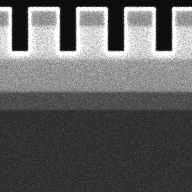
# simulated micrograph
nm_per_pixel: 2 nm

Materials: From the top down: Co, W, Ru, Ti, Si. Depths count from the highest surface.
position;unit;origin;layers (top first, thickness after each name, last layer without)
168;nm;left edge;Co 36, W 66, Ru 66, Ti 36, Si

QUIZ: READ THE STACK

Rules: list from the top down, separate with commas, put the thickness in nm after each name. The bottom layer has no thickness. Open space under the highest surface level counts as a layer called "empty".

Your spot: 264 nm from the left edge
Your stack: Co 36, W 66, Ru 66, Ti 36, Si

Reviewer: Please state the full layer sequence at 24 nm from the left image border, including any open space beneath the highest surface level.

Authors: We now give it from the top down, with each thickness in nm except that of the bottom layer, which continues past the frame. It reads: empty 88, W 14, Ru 66, Ti 36, Si